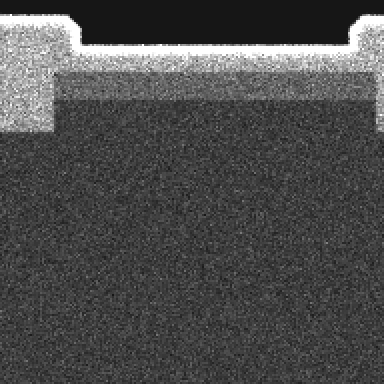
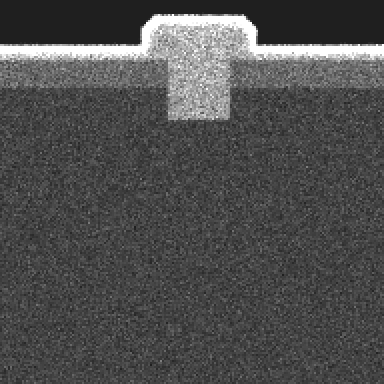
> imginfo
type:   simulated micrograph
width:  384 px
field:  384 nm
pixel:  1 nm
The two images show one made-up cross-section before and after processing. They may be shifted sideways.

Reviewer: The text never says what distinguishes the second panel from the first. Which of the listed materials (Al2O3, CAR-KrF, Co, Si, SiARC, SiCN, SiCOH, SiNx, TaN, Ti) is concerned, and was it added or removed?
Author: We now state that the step removed Al2O3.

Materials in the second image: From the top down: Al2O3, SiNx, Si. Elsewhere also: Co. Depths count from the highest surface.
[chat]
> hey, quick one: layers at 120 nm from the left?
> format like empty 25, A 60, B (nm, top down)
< empty 30, Al2O3 14, SiNx 28, Si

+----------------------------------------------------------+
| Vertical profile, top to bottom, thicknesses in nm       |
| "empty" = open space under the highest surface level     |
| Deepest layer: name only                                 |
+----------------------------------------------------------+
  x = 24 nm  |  empty 30, Al2O3 14, SiNx 28, Si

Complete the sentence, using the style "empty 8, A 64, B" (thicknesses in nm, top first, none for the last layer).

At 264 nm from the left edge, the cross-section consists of empty 30, Al2O3 14, SiNx 28, Si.